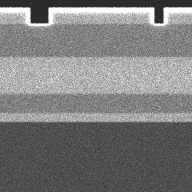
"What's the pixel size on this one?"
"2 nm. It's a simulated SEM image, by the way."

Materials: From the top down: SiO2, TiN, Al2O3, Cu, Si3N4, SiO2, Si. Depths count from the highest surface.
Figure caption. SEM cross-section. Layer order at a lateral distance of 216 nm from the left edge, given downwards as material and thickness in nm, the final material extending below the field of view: SiO2 32, TiN 66, Al2O3 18, Cu 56, Si3N4 38, SiO2 18, Si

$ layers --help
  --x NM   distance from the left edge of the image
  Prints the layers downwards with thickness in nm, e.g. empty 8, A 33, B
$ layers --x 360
SiO2 32, TiN 66, Al2O3 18, Cu 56, Si3N4 38, SiO2 18, Si